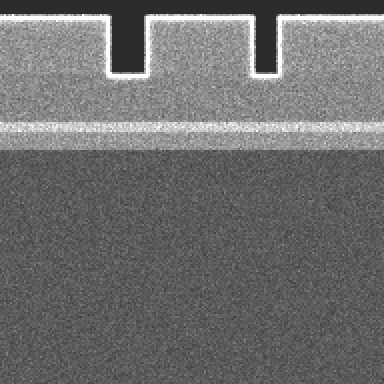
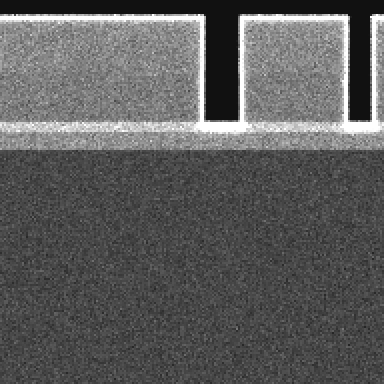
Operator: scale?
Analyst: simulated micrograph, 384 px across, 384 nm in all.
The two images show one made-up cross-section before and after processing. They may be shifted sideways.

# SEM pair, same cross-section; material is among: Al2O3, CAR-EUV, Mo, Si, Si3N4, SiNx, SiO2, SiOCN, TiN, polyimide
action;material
removed;SiNx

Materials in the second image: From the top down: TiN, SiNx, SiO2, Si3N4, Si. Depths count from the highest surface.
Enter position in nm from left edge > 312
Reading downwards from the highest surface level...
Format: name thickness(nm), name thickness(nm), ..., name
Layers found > TiN 58, SiNx 48, SiO2 10, Si3N4 18, Si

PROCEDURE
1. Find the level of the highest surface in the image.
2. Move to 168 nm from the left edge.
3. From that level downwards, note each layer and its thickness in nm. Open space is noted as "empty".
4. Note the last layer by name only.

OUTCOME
TiN 58, SiNx 48, SiO2 10, Si3N4 18, Si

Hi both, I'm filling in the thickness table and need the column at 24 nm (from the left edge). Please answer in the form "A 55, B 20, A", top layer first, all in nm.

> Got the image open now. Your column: TiN 58, SiNx 48, SiO2 10, Si3N4 18, Si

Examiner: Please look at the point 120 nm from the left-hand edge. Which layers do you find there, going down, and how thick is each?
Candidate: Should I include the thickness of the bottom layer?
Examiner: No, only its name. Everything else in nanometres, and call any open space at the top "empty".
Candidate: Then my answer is TiN 58, SiNx 48, SiO2 10, Si3N4 18, Si